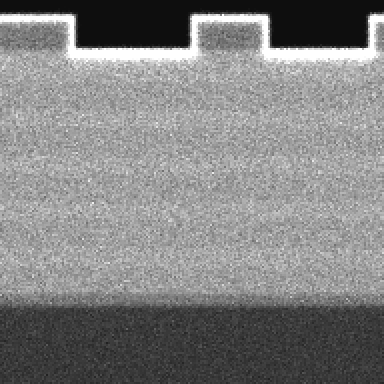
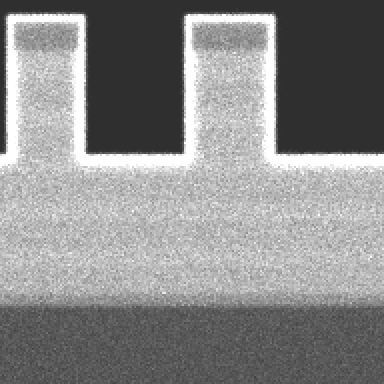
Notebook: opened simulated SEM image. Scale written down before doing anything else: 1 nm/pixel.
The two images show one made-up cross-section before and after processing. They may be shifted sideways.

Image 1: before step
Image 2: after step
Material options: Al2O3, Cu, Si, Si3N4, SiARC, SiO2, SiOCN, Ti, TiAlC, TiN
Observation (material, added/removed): Al2O3 and SiO2, removed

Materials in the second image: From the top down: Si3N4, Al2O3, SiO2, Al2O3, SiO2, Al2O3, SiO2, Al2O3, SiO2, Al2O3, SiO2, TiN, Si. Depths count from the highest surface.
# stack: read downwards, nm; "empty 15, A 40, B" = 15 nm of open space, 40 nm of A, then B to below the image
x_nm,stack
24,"Si3N4 34, Al2O3 32, SiO2 28, Al2O3 18, SiO2 28, Al2O3 18, SiO2 28, Al2O3 18, SiO2 28, Al2O3 18, SiO2 28, TiN 12, Si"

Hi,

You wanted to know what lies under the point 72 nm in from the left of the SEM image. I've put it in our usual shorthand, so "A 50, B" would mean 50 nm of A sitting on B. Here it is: Si3N4 34, Al2O3 32, SiO2 28, Al2O3 18, SiO2 28, Al2O3 18, SiO2 28, Al2O3 18, SiO2 28, Al2O3 18, SiO2 28, TiN 12, Si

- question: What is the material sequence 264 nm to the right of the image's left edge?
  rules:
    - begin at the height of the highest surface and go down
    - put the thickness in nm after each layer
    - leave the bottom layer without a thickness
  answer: Si3N4 34, Al2O3 32, SiO2 28, Al2O3 18, SiO2 28, Al2O3 18, SiO2 28, Al2O3 18, SiO2 28, Al2O3 18, SiO2 28, TiN 12, Si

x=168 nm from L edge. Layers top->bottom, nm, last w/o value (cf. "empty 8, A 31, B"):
empty 140, Al2O3 18, SiO2 28, Al2O3 18, SiO2 28, Al2O3 18, SiO2 28, TiN 12, Si